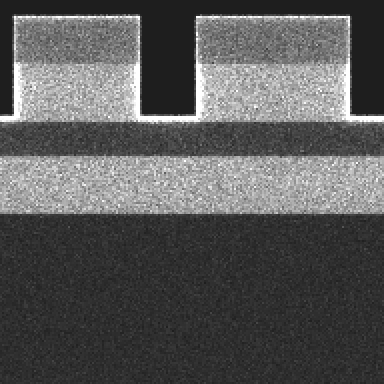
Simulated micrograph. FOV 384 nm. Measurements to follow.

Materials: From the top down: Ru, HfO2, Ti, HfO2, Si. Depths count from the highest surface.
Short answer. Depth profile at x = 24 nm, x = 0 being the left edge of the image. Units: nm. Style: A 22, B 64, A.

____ Ru 48, HfO2 58, Ti 34, HfO2 58, Si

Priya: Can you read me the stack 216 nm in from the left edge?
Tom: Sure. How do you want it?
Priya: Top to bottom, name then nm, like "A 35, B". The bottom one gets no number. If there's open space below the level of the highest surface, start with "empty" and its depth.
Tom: Ru 48, HfO2 58, Ti 34, HfO2 58, Si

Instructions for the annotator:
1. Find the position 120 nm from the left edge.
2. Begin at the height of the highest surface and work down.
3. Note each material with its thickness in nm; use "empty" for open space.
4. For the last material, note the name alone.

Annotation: Ru 48, HfO2 58, Ti 34, HfO2 58, Si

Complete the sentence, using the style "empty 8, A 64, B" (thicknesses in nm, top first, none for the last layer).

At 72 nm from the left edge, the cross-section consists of Ru 48, HfO2 58, Ti 34, HfO2 58, Si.